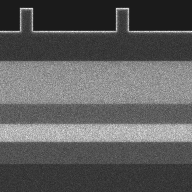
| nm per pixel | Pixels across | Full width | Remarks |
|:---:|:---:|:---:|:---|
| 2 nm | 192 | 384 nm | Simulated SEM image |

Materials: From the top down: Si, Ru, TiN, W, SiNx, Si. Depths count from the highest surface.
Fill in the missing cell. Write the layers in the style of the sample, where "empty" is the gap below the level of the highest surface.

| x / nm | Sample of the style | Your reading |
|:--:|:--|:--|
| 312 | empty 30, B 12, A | empty 46, Si 60, Ru 86, TiN 40, W 36, SiNx 44, Si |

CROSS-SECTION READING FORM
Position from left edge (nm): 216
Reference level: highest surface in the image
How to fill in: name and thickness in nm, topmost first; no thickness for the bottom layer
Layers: empty 46, Si 60, Ru 86, TiN 40, W 36, SiNx 44, Si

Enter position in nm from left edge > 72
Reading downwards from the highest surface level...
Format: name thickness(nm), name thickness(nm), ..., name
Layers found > empty 46, Si 60, Ru 86, TiN 40, W 36, SiNx 44, Si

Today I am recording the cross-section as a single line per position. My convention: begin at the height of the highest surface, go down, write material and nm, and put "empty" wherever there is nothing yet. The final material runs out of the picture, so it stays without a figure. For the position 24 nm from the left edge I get empty 46, Si 60, Ru 86, TiN 40, W 36, SiNx 44, Si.